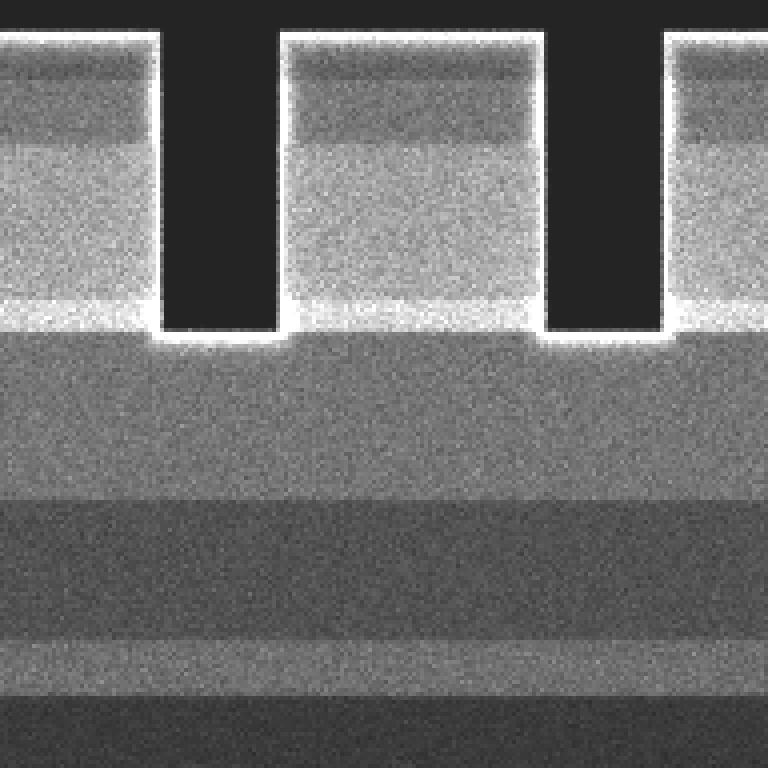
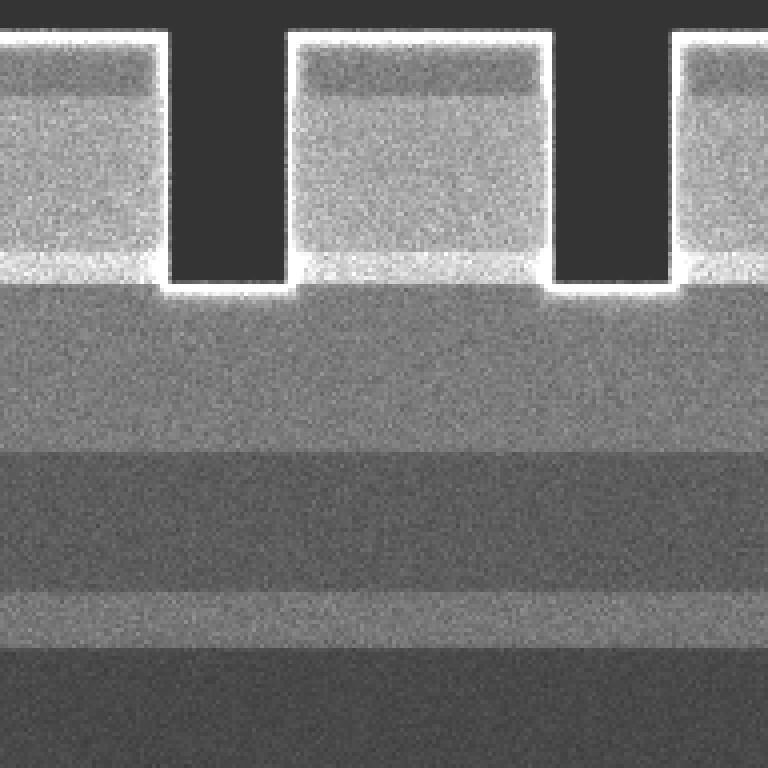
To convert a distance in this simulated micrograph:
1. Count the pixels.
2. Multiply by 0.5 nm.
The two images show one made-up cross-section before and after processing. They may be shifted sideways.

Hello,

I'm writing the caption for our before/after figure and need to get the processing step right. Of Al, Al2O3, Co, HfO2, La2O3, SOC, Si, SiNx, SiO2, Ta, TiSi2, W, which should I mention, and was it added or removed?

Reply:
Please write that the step removed SOC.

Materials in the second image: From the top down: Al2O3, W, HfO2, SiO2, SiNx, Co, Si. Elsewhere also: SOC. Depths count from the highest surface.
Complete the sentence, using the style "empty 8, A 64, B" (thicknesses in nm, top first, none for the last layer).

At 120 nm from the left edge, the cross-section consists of empty 126, SiO2 84, SiNx 70, Co 28, Si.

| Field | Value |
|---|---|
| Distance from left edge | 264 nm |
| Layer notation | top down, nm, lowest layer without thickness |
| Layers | Al2O3 32, W 78, HfO2 16, SiO2 84, SiNx 70, Co 28, Si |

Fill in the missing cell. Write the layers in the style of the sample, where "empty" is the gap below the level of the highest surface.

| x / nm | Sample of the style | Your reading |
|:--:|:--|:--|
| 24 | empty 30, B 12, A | Al2O3 32, W 78, HfO2 16, SiO2 84, SiNx 70, Co 28, Si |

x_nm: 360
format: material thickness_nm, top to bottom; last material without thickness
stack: Al2O3 32, W 78, HfO2 16, SiO2 84, SiNx 70, Co 28, Si